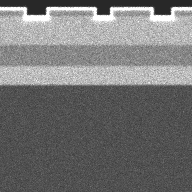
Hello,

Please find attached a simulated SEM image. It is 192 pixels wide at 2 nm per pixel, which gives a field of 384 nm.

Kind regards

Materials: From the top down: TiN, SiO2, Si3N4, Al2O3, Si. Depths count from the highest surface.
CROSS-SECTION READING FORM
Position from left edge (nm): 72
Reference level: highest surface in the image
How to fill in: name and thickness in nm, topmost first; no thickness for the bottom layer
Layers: empty 16, SiO2 58, Si3N4 42, Al2O3 38, Si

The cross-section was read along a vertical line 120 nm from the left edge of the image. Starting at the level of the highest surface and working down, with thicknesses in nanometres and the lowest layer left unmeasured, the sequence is TiN 16, SiO2 58, Si3N4 42, Al2O3 38, Si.